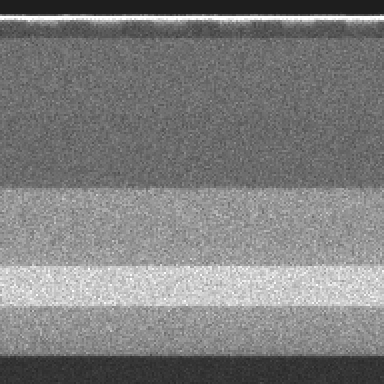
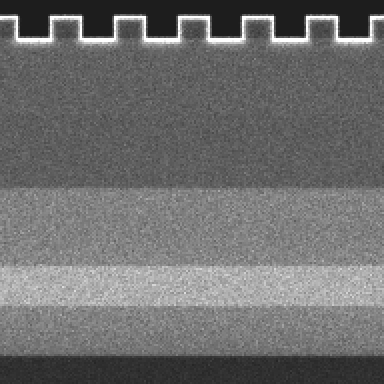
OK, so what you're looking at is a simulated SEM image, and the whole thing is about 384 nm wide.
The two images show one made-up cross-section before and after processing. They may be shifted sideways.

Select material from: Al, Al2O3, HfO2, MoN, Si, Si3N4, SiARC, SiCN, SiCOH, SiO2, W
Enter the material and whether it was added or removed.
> SiARC / removed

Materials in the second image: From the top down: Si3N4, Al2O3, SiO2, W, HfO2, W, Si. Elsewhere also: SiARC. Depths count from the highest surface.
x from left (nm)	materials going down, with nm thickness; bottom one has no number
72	Si3N4 22, Al2O3 76, SiO2 74, W 78, HfO2 40, W 50, Si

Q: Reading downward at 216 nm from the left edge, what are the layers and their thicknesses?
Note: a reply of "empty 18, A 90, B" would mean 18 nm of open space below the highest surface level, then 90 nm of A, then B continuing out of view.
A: empty 22, Al2O3 76, SiO2 74, W 78, HfO2 40, W 50, Si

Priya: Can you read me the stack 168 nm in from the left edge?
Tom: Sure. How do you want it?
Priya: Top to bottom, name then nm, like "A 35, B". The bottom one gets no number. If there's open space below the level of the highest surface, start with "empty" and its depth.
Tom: empty 22, Al2O3 76, SiO2 74, W 78, HfO2 40, W 50, Si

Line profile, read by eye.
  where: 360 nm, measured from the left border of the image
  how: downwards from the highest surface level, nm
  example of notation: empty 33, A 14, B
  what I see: empty 22, Al2O3 76, SiO2 74, W 78, HfO2 40, W 50, Si